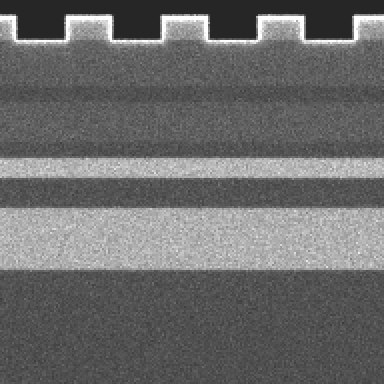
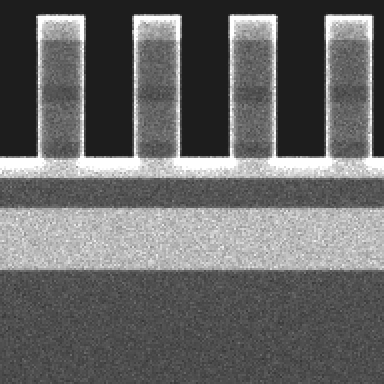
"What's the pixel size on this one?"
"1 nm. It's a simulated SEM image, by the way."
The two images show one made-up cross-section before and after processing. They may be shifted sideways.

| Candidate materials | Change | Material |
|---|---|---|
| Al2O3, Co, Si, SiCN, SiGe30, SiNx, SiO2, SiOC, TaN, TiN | removed | Si and SiGe30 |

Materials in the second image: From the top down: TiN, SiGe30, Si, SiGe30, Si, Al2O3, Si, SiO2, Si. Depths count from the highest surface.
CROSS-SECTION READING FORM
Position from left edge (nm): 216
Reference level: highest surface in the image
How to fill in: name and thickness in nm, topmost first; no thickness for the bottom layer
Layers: empty 142, Al2O3 20, Si 30, SiO2 62, Si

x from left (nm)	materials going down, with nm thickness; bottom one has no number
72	TiN 24, SiGe30 46, Si 16, SiGe30 40, Si 16, Al2O3 20, Si 30, SiO2 62, Si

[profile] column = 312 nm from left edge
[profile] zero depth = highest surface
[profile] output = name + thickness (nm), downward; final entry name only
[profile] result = empty 142, Al2O3 20, Si 30, SiO2 62, Si